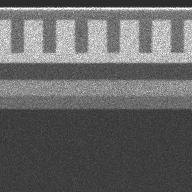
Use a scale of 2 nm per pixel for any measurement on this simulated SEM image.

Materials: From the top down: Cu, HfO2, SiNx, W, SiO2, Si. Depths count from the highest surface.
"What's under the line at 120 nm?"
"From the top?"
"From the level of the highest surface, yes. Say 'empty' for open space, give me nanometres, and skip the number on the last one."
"Cu 24, HfO2 86, SiNx 34, W 32, SiO2 26, Si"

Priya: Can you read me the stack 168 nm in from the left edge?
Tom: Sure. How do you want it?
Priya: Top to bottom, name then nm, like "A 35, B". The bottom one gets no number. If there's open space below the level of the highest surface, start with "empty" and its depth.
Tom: Cu 90, HfO2 20, SiNx 34, W 32, SiO2 26, Si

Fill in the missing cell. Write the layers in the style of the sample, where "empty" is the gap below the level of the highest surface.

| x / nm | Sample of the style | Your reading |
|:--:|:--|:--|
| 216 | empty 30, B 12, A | Cu 90, HfO2 20, SiNx 34, W 32, SiO2 26, Si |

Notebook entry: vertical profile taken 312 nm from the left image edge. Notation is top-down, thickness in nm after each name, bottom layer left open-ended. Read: Cu 24, HfO2 86, SiNx 34, W 32, SiO2 26, Si